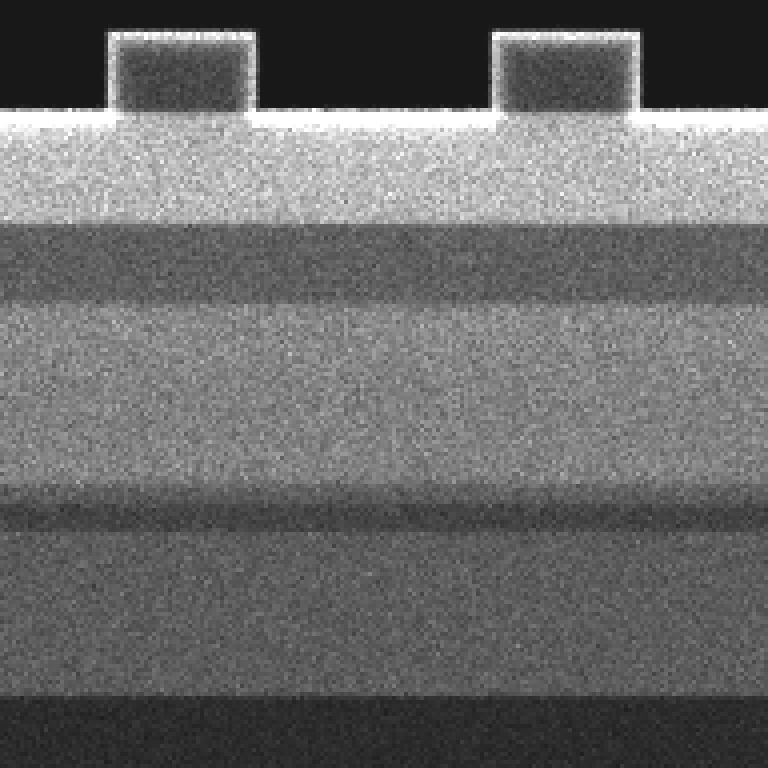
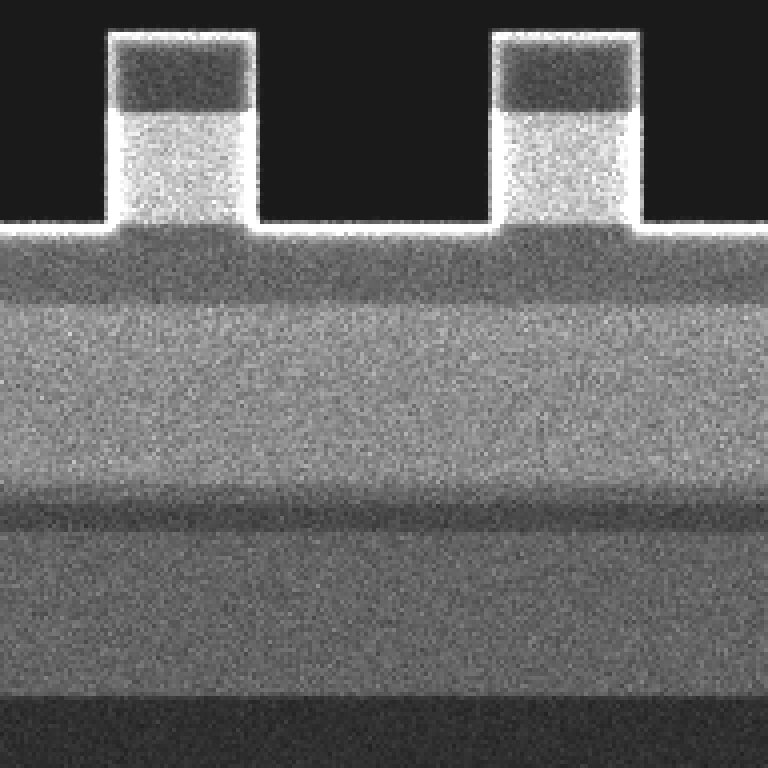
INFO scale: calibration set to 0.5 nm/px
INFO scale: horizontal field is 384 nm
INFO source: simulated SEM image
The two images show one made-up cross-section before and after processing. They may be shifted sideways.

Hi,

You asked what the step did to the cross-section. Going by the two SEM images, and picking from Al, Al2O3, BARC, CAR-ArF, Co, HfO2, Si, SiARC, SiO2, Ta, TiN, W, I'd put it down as HfO2, removed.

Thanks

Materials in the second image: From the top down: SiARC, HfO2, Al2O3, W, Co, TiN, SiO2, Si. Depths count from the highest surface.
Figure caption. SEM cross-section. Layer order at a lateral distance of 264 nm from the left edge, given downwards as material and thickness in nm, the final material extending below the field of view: SiARC 40, HfO2 56, Al2O3 40, W 90, Co 10, TiN 14, SiO2 82, Si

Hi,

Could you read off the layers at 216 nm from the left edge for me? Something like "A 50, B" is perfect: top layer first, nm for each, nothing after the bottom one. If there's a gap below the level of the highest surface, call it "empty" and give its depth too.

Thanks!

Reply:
empty 96, Al2O3 40, W 90, Co 10, TiN 14, SiO2 82, Si